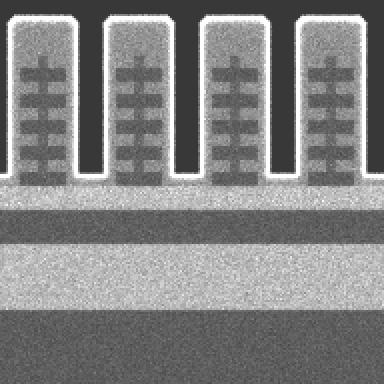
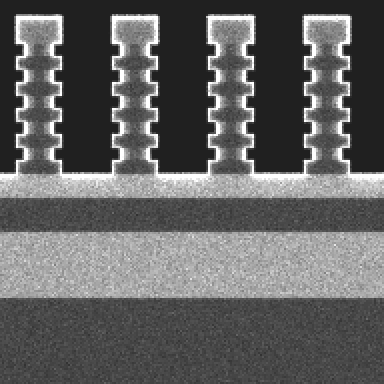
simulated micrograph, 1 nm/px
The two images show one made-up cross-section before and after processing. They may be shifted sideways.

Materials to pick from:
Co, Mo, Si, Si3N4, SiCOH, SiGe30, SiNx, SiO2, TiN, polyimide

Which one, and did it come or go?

Si3N4 - removed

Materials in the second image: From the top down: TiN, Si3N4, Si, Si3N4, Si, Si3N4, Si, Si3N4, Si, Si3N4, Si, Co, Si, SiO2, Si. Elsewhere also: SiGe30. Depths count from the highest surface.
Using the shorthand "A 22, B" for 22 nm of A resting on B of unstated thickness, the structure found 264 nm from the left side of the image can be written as empty 158, Co 24, Si 34, SiO2 66, Si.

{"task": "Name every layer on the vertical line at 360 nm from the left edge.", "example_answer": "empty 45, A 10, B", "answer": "empty 158, Co 24, Si 34, SiO2 66, Si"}